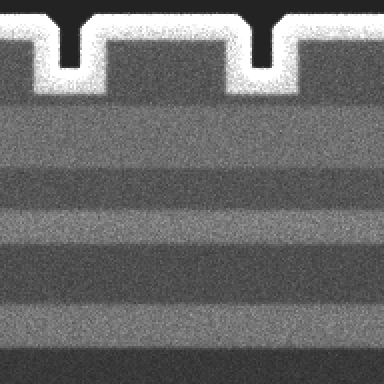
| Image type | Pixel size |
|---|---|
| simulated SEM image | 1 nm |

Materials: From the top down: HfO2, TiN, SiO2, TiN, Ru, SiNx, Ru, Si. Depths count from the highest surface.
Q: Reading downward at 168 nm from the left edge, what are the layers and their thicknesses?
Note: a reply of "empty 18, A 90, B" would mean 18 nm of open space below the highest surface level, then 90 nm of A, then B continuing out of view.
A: HfO2 24, TiN 66, SiO2 62, TiN 42, Ru 34, SiNx 60, Ru 44, Si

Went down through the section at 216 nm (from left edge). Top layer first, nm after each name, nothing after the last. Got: HfO2 24, TiN 66, SiO2 62, TiN 42, Ru 34, SiNx 60, Ru 44, Si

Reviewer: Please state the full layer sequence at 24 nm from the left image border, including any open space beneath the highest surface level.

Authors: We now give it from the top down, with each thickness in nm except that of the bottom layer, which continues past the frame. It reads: HfO2 24, TiN 66, SiO2 62, TiN 42, Ru 34, SiNx 60, Ru 44, Si